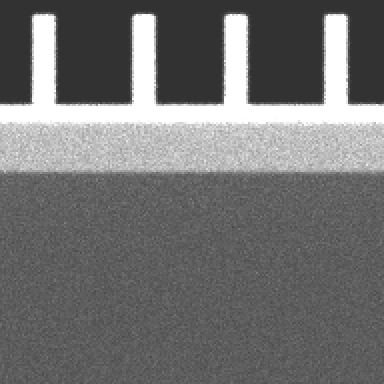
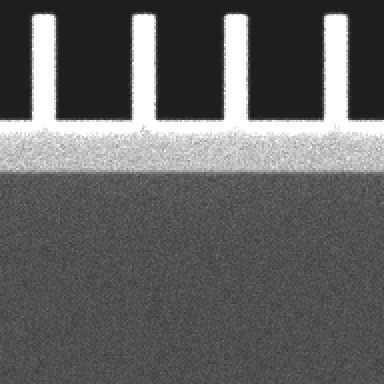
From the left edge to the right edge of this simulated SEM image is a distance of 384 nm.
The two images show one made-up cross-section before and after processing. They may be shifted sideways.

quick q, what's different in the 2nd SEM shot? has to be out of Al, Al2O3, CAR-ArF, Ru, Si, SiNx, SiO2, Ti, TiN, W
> Ru removed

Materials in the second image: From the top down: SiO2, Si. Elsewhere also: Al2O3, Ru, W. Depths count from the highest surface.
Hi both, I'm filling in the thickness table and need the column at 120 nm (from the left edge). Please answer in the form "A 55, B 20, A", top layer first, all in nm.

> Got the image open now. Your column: empty 106, SiO2 50, Si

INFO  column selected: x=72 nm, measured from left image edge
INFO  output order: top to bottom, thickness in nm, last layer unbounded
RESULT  empty 106, SiO2 50, Si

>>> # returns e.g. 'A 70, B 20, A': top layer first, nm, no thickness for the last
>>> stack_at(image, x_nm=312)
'empty 106, SiO2 50, Si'